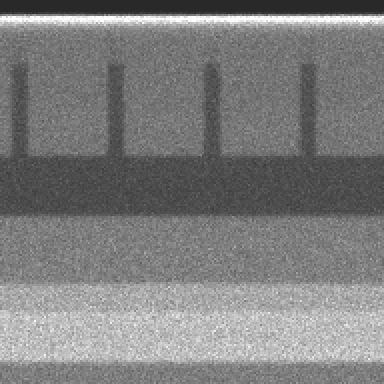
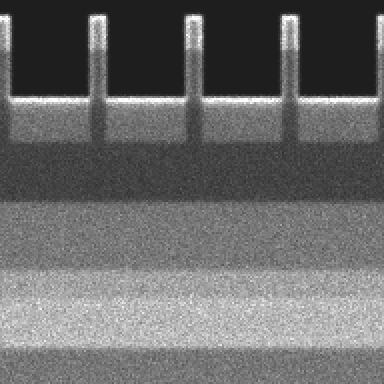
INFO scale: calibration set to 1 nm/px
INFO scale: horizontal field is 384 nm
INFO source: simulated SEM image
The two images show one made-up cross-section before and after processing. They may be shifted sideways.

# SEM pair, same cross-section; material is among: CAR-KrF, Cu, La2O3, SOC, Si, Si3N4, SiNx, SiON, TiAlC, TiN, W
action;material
removed;SOC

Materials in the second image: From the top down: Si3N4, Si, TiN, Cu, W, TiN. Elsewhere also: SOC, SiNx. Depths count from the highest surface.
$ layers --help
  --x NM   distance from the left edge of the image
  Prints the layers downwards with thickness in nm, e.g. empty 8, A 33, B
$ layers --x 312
empty 82, Si3N4 44, Si 60, TiN 68, Cu 28, W 50, TiN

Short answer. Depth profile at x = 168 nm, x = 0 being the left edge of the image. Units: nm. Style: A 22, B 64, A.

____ empty 82, Si3N4 44, Si 60, TiN 68, Cu 28, W 50, TiN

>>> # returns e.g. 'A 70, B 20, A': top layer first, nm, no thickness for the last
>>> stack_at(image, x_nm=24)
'empty 82, Si3N4 44, Si 60, TiN 68, Cu 28, W 50, TiN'